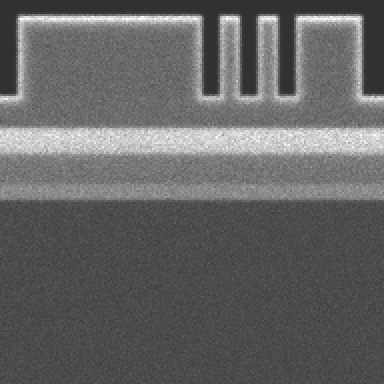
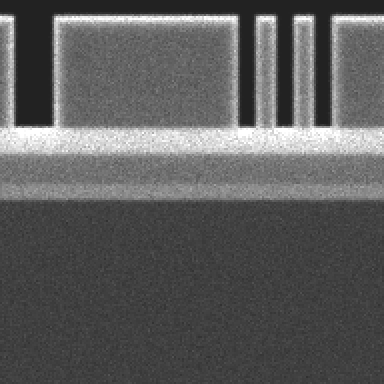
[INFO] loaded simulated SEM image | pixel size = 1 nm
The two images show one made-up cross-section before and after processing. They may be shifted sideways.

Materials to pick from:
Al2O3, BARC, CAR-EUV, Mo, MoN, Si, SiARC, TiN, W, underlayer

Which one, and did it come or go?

underlayer - removed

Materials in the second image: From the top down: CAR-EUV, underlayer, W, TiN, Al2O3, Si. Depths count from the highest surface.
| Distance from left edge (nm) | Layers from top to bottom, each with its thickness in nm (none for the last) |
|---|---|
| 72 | CAR-EUV 80, underlayer 32, W 26, TiN 30, Al2O3 16, Si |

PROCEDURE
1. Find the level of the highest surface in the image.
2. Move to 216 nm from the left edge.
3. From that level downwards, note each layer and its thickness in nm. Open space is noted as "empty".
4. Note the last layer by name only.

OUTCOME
CAR-EUV 80, underlayer 32, W 26, TiN 30, Al2O3 16, Si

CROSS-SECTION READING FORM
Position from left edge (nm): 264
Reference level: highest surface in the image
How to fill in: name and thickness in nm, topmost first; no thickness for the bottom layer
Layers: CAR-EUV 80, underlayer 32, W 26, TiN 30, Al2O3 16, Si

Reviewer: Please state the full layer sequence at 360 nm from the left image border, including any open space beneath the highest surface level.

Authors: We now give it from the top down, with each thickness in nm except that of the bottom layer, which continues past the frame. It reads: CAR-EUV 80, underlayer 32, W 26, TiN 30, Al2O3 16, Si